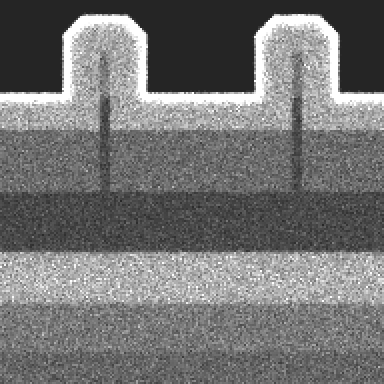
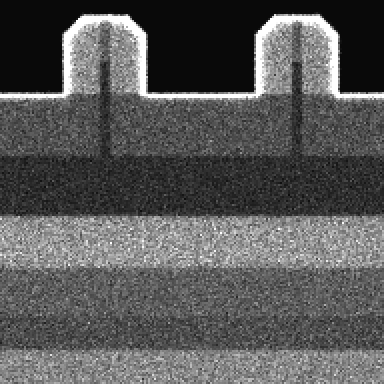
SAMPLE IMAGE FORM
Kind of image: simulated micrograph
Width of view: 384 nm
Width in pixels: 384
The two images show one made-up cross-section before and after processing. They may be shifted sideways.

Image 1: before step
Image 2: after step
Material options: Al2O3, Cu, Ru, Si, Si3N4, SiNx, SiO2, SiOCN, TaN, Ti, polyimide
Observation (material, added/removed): Al2O3, removed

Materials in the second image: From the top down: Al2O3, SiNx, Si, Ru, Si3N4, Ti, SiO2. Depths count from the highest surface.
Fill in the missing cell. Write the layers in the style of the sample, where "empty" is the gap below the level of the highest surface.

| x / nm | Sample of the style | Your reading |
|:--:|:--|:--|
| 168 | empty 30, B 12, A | empty 78, SiNx 62, Si 60, Ru 52, Si3N4 48, Ti 34, SiO2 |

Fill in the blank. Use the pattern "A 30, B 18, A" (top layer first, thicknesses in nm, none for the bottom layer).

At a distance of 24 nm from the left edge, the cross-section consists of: empty 78, SiNx 62, Si 60, Ru 52, Si3N4 48, Ti 34, SiO2